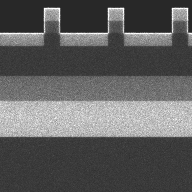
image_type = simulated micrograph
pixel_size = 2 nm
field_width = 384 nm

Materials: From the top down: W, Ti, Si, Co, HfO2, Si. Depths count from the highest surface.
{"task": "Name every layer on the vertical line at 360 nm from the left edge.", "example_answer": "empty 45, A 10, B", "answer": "W 26, Ti 24, Si 86, Co 50, HfO2 72, Si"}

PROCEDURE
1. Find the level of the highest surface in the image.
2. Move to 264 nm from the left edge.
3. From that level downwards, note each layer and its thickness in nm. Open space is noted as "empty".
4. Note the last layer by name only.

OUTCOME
empty 50, W 26, Si 60, Co 50, HfO2 72, Si